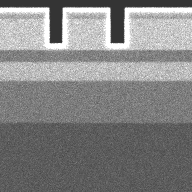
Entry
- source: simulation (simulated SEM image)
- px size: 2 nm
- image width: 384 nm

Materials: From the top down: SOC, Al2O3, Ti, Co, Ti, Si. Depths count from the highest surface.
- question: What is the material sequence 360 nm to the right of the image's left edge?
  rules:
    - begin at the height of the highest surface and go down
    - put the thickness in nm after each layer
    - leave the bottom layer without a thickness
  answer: SOC 22, Al2O3 62, Ti 24, Co 38, Ti 84, Si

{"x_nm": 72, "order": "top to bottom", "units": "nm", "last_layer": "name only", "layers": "SOC 22, Al2O3 62, Ti 24, Co 38, Ti 84, Si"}